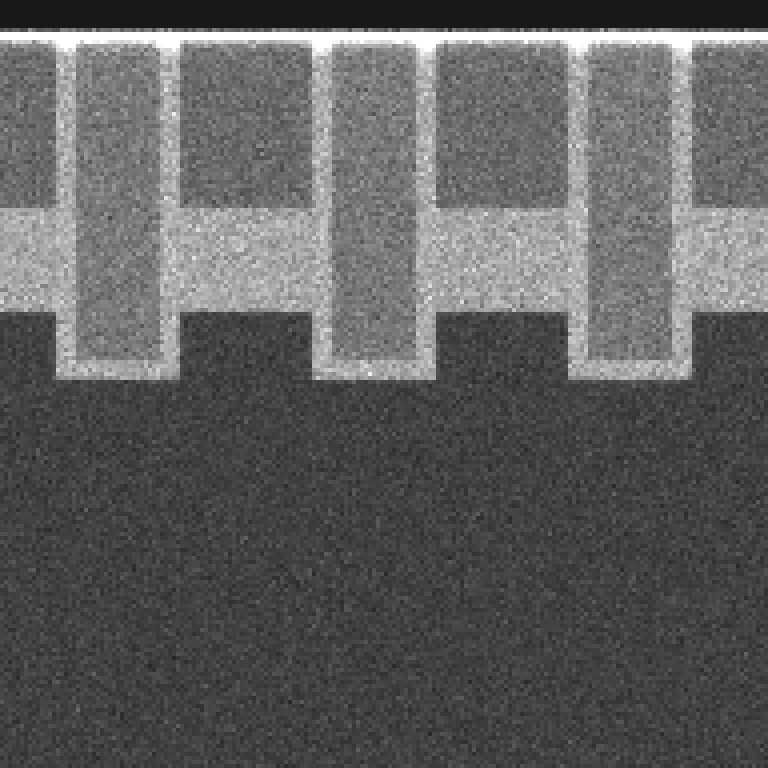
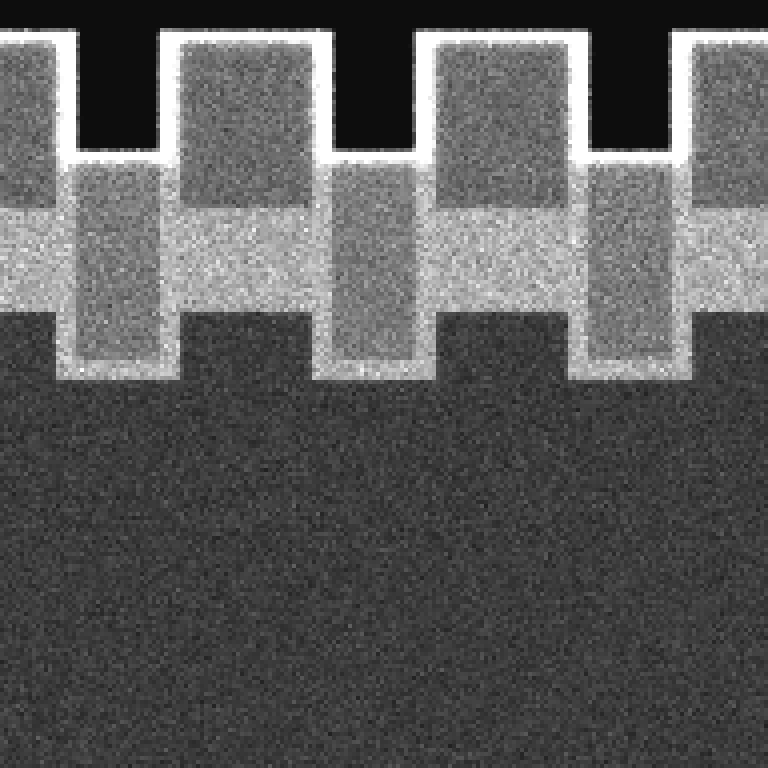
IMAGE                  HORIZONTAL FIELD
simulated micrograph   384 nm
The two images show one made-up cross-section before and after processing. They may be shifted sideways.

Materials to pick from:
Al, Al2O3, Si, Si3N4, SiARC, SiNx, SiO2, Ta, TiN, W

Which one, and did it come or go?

Si3N4 - removed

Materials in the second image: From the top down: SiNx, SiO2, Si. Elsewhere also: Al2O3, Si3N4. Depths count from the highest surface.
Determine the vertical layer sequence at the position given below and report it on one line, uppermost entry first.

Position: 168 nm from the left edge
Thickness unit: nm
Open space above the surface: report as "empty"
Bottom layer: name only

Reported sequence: empty 60, Si3N4 104, Al2O3 10, Si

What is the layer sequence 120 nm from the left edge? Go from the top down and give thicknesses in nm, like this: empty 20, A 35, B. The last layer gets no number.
SiNx 88, SiO2 52, Si